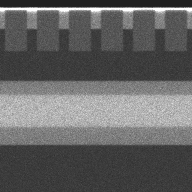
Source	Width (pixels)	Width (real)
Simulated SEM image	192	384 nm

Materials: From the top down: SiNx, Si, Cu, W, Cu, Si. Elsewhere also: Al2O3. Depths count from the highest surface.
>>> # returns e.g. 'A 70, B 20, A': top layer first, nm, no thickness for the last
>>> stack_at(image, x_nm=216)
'SiNx 86, Si 60, Cu 28, W 64, Cu 36, Si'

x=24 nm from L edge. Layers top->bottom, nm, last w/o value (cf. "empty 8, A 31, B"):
SiNx 86, Si 60, Cu 28, W 64, Cu 36, Si